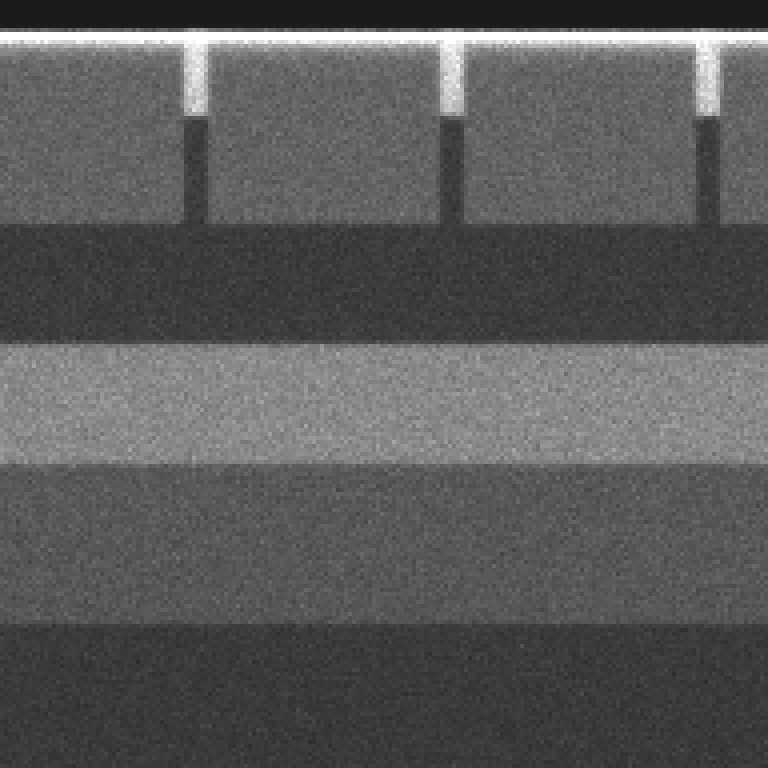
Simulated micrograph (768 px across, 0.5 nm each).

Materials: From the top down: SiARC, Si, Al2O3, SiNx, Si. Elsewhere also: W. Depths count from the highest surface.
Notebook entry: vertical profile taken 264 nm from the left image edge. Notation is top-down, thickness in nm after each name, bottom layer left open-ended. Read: SiARC 96, Si 60, Al2O3 60, SiNx 80, Si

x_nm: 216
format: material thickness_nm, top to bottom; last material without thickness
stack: SiARC 96, Si 60, Al2O3 60, SiNx 80, Si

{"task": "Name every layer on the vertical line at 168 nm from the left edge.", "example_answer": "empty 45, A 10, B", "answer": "SiARC 96, Si 60, Al2O3 60, SiNx 80, Si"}